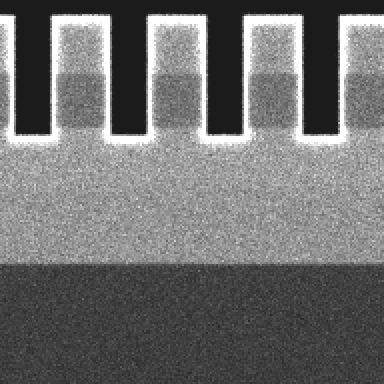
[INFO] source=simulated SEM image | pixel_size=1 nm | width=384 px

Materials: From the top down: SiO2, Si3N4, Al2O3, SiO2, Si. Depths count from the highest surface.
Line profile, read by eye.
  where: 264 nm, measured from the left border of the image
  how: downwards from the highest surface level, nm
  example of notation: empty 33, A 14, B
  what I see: SiO2 58, Si3N4 54, Al2O3 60, SiO2 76, Si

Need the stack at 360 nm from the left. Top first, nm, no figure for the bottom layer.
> SiO2 58, Si3N4 54, Al2O3 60, SiO2 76, Si